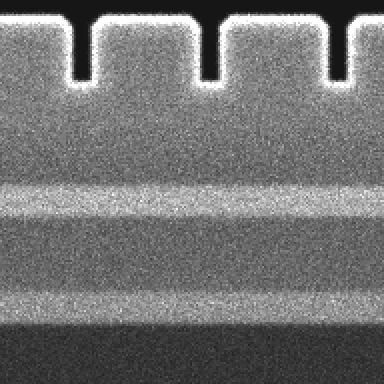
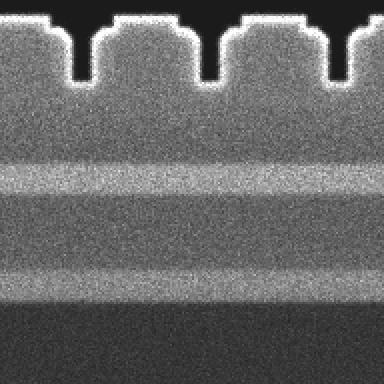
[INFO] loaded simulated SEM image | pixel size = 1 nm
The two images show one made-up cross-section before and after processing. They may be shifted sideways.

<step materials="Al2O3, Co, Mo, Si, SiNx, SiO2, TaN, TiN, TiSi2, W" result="removed Al2O3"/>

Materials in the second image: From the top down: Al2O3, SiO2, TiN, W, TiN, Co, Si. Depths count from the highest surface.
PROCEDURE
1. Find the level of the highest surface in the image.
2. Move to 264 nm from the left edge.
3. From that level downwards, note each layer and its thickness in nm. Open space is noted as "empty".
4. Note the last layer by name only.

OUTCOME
SiO2 90, TiN 58, W 30, TiN 76, Co 32, Si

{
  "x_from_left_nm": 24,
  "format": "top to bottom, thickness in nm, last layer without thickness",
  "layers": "SiO2 90, TiN 58, W 30, TiN 76, Co 32, Si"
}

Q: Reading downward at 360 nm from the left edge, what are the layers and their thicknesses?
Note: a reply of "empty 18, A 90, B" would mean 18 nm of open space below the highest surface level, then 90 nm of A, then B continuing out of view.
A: empty 12, Al2O3 54, SiO2 24, TiN 58, W 30, TiN 76, Co 32, Si